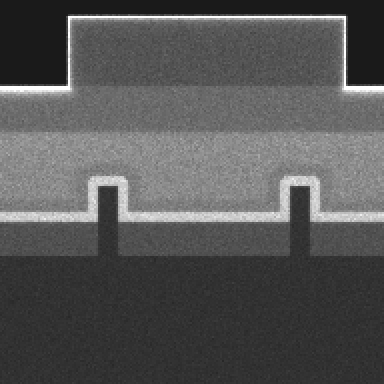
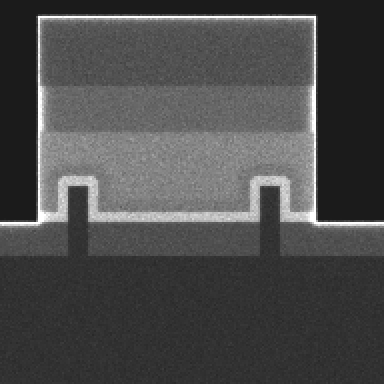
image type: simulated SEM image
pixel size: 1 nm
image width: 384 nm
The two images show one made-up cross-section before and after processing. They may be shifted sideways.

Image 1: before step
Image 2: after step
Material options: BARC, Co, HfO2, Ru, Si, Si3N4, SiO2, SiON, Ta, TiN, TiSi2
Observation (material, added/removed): Co and HfO2 and Ru and SiO2, removed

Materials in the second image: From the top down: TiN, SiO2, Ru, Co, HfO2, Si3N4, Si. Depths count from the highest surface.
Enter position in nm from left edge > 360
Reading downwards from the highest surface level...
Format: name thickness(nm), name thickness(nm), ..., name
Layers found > empty 206, Si3N4 34, Si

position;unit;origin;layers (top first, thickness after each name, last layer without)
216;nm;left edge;TiN 70, SiO2 46, Ru 68, Co 12, HfO2 10, Si3N4 34, Si